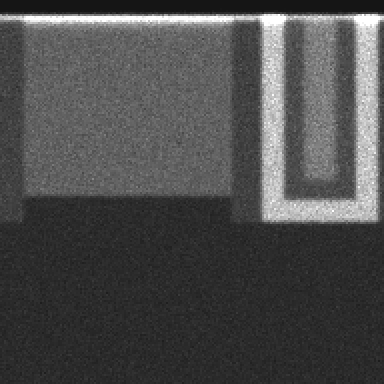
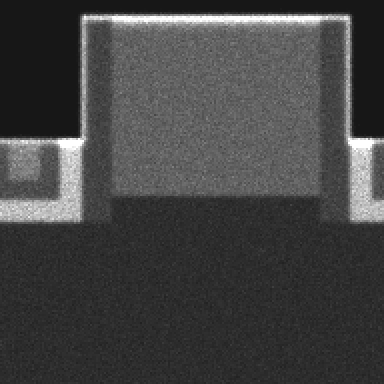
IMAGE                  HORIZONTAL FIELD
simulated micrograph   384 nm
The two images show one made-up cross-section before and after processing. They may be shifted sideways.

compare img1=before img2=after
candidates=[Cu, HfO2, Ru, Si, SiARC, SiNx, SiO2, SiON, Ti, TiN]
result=removed:HfO2 and Ru and TiN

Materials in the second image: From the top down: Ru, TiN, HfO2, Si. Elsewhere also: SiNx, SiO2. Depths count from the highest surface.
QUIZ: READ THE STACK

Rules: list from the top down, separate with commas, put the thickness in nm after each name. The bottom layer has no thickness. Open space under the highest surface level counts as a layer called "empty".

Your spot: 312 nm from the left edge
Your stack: SiO2 180, Si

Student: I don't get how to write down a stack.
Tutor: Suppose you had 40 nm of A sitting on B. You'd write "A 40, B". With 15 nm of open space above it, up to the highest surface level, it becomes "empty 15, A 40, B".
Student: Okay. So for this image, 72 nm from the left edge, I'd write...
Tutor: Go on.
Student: empty 124, HfO2 82, Si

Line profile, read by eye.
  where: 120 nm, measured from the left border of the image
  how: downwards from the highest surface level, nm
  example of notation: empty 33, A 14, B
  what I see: SiO2 180, Si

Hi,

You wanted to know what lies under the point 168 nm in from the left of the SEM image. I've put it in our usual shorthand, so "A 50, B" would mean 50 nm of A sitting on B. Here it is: SiO2 180, Si